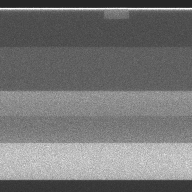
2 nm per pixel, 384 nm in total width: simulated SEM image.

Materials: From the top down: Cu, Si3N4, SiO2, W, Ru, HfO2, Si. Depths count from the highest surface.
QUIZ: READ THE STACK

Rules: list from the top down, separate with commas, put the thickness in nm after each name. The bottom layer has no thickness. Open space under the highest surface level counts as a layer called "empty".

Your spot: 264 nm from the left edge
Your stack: Si3N4 78, SiO2 88, W 50, Ru 54, HfO2 74, Si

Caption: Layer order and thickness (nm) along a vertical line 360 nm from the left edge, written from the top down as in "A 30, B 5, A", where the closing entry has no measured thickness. Si3N4 78, SiO2 88, W 50, Ru 54, HfO2 74, Si